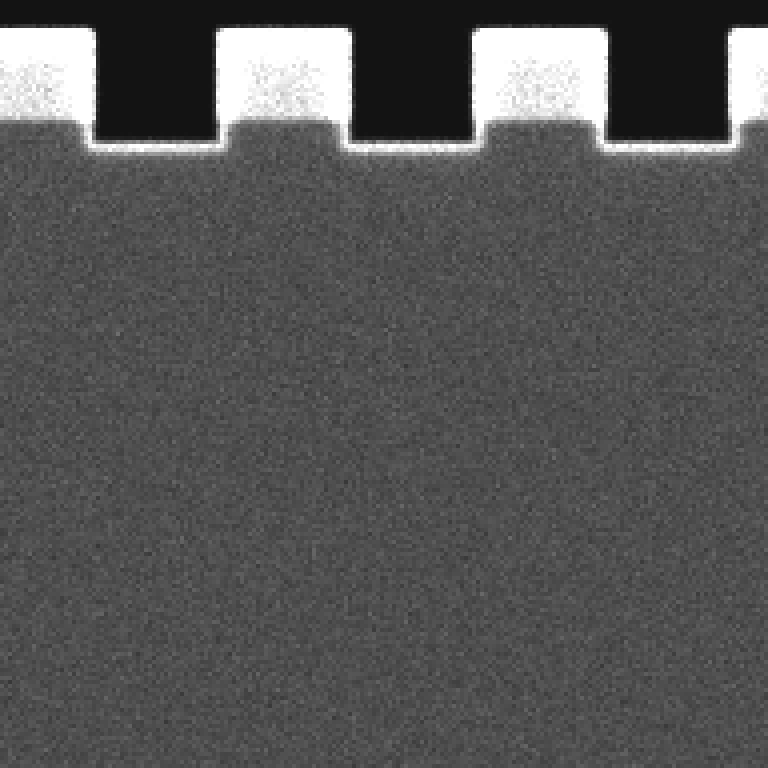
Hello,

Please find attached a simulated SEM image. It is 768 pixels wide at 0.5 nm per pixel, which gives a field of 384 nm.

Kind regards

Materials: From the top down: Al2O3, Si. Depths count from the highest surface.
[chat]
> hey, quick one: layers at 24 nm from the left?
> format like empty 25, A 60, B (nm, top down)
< Al2O3 44, Si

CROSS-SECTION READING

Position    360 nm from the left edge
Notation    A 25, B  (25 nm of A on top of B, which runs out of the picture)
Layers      empty 56, Si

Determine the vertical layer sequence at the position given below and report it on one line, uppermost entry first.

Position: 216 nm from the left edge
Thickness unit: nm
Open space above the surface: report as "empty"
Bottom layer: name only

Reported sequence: empty 56, Si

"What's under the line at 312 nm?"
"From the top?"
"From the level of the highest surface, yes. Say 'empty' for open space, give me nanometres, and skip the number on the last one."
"empty 56, Si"